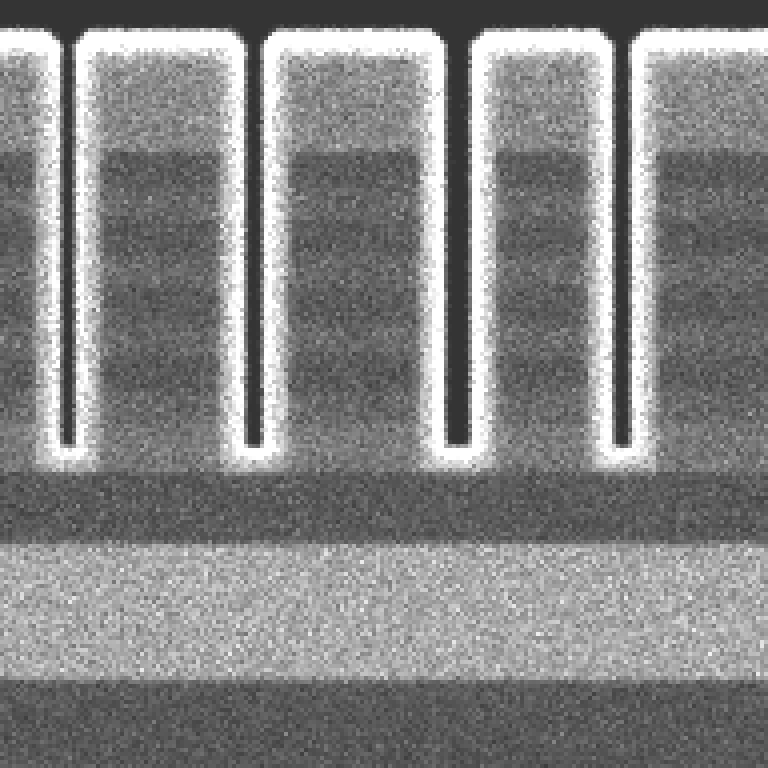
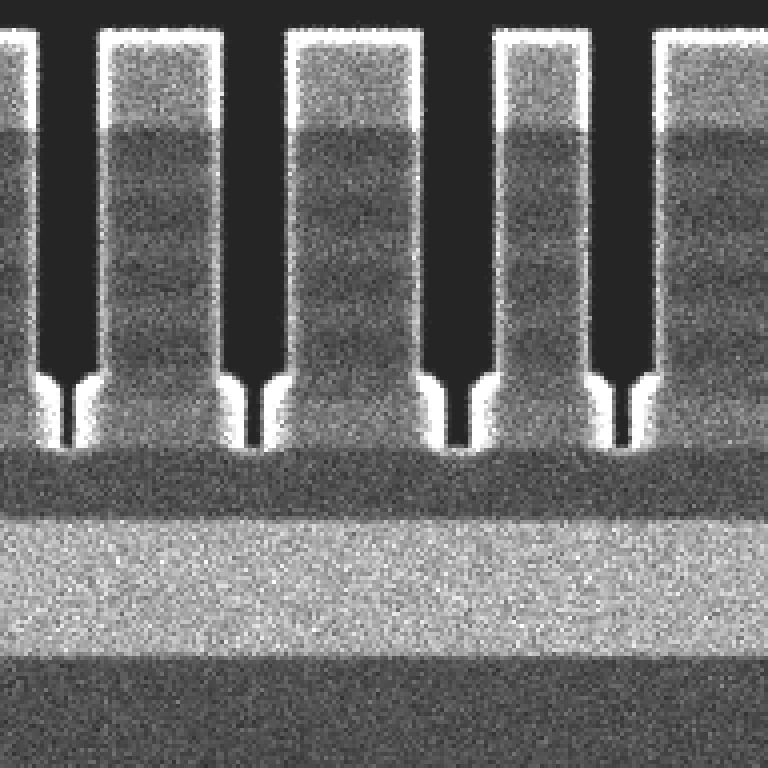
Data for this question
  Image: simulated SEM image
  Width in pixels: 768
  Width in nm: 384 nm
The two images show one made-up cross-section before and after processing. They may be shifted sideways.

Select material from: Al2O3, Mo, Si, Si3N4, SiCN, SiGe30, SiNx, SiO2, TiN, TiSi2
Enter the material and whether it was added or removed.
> SiO2 / removed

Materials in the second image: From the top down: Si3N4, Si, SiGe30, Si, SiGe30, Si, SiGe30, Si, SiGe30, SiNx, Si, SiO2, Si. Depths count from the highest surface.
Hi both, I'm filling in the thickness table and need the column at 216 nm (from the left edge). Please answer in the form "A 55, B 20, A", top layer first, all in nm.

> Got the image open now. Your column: empty 174, SiO2 34, Si 36, SiO2 68, Si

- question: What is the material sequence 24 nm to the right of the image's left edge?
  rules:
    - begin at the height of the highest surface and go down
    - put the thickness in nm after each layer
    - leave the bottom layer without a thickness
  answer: empty 174, SiO2 34, Si 36, SiO2 68, Si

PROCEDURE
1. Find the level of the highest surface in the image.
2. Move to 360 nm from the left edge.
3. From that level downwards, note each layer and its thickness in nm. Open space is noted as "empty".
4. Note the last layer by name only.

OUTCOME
Si3N4 48, Si 18, SiGe30 16, Si 18, SiGe30 16, Si 18, SiGe30 16, Si 18, SiGe30 16, SiNx 24, Si 36, SiO2 68, Si